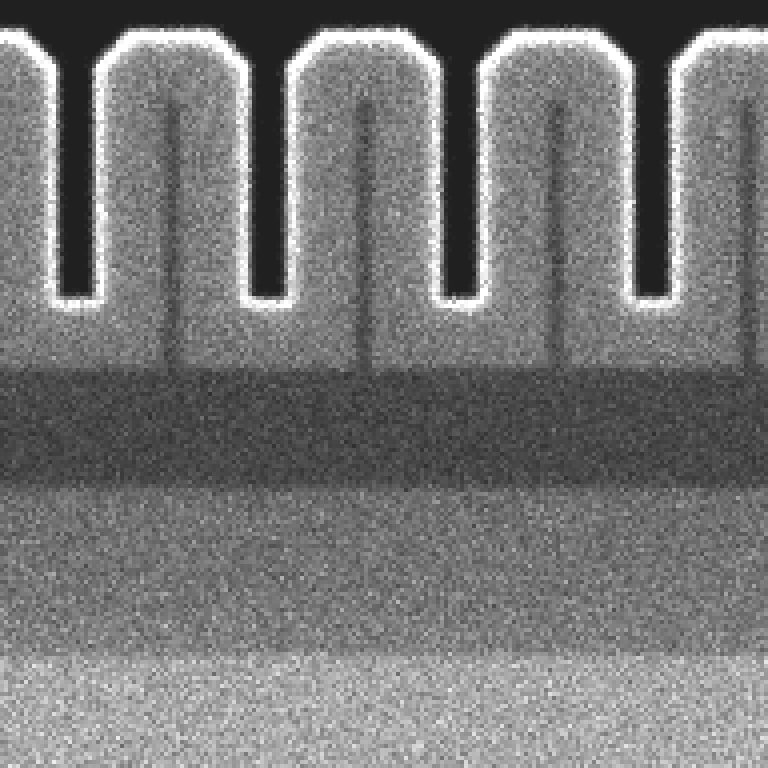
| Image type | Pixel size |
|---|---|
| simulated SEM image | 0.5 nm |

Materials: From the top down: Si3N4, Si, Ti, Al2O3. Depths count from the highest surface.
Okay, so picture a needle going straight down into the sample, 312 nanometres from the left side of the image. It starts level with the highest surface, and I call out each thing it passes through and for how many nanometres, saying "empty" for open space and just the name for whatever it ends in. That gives empty 14, Si3N4 154, Si 60, Ti 84, Al2O3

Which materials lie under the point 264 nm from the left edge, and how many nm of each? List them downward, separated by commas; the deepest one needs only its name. Si3N4 168, Si 60, Ti 84, Al2O3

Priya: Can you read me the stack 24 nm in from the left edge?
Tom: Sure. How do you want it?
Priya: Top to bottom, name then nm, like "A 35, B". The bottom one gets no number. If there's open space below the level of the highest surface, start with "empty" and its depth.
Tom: empty 14, Si3N4 154, Si 60, Ti 84, Al2O3